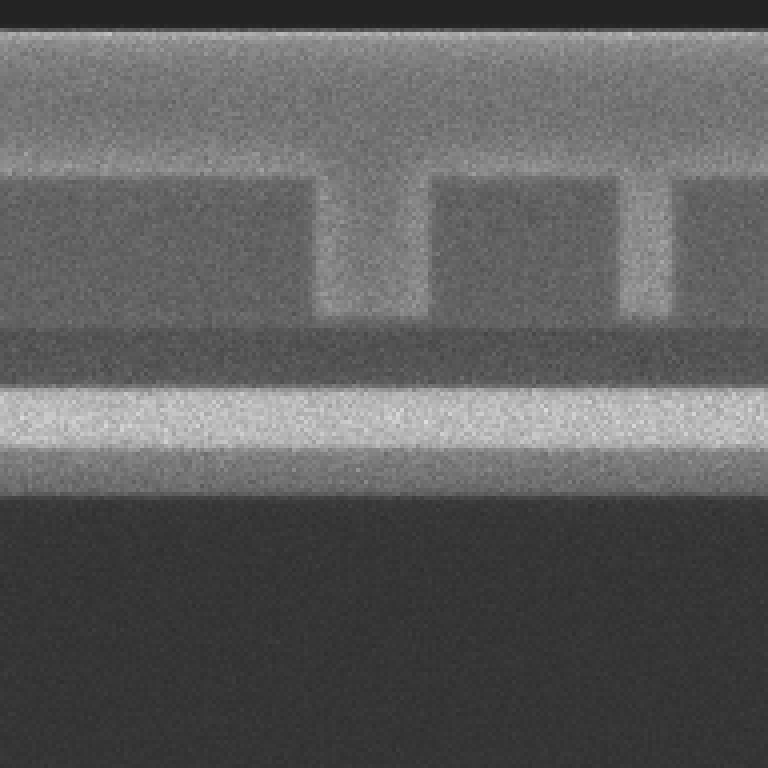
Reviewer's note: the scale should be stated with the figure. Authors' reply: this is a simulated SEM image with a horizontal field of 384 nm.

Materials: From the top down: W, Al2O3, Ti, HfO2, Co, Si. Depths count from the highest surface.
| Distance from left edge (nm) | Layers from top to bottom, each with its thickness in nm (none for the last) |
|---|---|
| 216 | W 72, Al2O3 76, Ti 30, HfO2 30, Co 24, Si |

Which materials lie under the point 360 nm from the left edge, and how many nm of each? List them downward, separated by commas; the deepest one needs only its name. W 72, Al2O3 76, Ti 30, HfO2 30, Co 24, Si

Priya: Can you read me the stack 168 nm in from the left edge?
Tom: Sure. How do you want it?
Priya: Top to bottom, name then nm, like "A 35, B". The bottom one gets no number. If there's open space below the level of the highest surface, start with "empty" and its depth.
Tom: W 142, Al2O3 6, Ti 30, HfO2 30, Co 24, Si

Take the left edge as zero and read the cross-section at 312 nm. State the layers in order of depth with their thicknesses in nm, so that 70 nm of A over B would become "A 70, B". W 142, Al2O3 6, Ti 30, HfO2 30, Co 24, Si